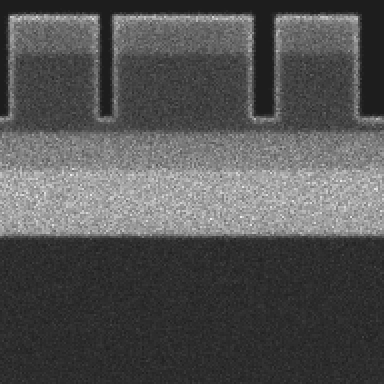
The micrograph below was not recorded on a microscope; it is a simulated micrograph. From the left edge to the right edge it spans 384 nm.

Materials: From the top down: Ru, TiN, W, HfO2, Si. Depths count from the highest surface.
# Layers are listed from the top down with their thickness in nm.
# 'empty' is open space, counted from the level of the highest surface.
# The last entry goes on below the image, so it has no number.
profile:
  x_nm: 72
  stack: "Ru 38, TiN 78, W 38, HfO2 66, Si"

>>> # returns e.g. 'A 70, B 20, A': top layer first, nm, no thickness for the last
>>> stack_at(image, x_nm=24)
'Ru 38, TiN 78, W 38, HfO2 66, Si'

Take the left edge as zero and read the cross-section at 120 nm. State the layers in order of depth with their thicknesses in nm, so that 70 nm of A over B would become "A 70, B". Ru 38, TiN 78, W 38, HfO2 66, Si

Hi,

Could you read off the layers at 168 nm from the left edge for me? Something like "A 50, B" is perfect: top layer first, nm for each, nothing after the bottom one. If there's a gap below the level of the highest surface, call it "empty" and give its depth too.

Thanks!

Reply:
Ru 38, TiN 78, W 38, HfO2 66, Si